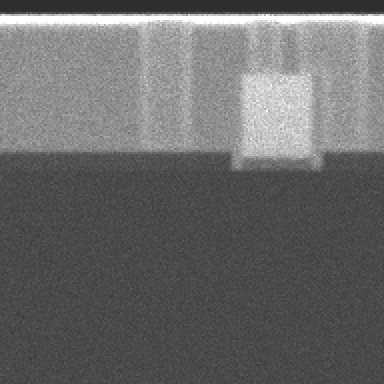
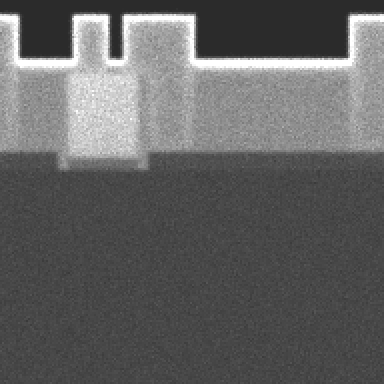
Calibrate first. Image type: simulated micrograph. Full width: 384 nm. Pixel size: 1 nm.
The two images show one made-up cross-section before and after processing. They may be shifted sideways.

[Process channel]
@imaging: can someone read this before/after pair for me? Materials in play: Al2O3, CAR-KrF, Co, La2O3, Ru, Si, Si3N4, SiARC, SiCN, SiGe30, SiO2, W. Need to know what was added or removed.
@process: SiO2 removed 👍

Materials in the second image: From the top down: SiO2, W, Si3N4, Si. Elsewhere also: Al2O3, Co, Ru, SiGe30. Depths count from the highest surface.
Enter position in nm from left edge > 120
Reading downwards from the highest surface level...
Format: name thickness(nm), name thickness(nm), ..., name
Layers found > empty 44, SiO2 14, W 84, Si3N4 12, Si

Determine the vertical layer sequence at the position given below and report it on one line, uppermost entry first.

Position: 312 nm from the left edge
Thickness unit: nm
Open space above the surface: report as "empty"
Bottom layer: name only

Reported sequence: empty 44, SiO2 92, SiGe30 18, Si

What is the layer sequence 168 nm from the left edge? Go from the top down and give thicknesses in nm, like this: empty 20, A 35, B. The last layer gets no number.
Co 126, Ru 10, SiGe30 18, Si